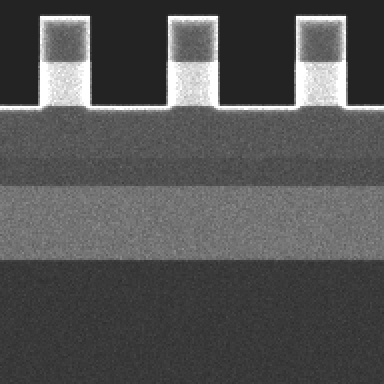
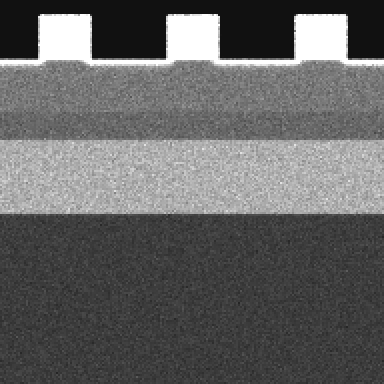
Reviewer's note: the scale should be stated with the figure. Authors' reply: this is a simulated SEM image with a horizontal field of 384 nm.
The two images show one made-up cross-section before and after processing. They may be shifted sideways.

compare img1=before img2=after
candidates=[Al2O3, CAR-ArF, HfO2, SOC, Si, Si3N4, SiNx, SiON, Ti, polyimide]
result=removed:SOC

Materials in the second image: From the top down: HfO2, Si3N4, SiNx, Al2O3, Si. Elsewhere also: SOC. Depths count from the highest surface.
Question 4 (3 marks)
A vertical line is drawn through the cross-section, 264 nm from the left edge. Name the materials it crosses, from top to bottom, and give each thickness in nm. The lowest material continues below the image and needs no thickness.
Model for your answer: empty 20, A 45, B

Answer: empty 44, Si3N4 52, SiNx 28, Al2O3 74, Si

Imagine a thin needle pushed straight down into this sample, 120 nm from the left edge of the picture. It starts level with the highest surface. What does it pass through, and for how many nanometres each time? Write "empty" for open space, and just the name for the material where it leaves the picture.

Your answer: empty 44, Si3N4 52, SiNx 28, Al2O3 74, Si